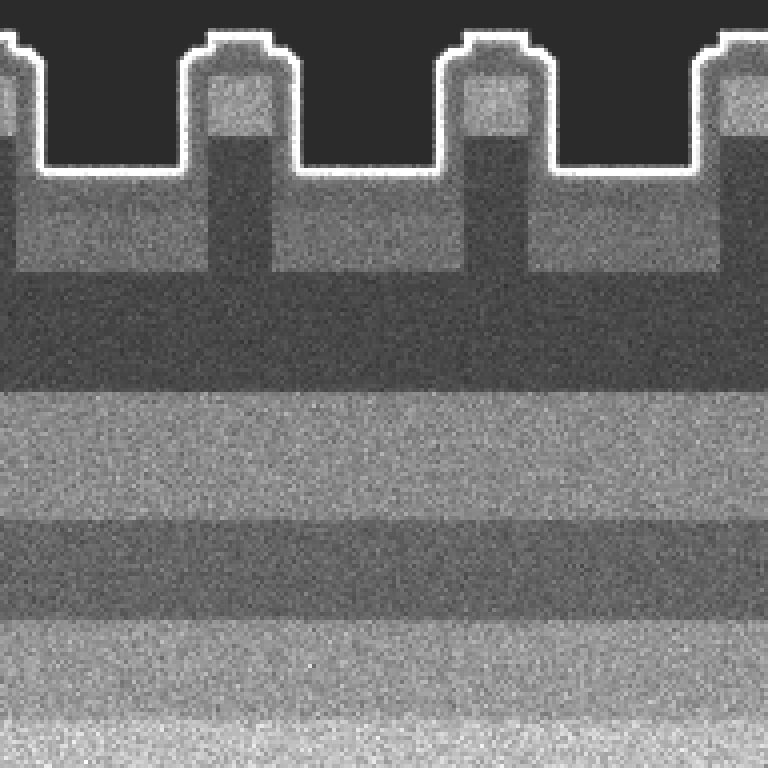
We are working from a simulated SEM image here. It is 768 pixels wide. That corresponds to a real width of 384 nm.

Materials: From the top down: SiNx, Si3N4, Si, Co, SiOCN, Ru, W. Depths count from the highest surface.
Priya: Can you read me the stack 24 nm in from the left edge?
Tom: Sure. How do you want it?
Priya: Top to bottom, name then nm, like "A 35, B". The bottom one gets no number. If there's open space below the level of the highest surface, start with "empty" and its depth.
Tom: empty 68, SiNx 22, Si3N4 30, Si 60, Co 64, SiOCN 50, Ru 50, W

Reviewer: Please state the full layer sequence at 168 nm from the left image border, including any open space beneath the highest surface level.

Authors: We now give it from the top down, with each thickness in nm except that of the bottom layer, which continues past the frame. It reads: empty 68, SiNx 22, Si3N4 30, Si 60, Co 64, SiOCN 50, Ru 50, W